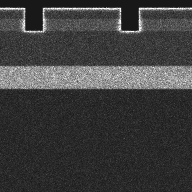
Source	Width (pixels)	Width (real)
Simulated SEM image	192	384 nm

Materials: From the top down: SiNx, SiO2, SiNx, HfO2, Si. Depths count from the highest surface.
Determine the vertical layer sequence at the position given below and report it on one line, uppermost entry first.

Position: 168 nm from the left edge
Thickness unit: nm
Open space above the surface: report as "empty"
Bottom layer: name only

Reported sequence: SiNx 22, SiO2 24, SiNx 70, HfO2 46, Si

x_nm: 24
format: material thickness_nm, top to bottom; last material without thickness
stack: SiNx 22, SiO2 24, SiNx 70, HfO2 46, Si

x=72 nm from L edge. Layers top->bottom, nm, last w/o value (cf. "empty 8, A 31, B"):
empty 46, SiNx 70, HfO2 46, Si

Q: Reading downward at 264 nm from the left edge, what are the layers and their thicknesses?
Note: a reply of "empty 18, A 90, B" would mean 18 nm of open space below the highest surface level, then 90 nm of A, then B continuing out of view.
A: empty 46, SiNx 70, HfO2 46, Si